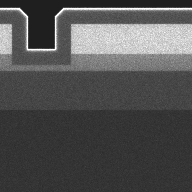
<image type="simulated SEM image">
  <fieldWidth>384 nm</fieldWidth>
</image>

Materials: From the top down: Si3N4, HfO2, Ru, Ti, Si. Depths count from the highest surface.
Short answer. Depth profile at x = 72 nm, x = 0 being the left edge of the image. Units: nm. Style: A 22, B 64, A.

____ empty 82, Si3N4 32, Ru 12, Ti 78, Si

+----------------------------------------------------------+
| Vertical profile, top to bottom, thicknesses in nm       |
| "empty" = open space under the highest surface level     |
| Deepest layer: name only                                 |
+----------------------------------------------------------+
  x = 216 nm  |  Si3N4 32, HfO2 60, Ru 34, Ti 78, Si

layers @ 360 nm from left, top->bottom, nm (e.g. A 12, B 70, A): Si3N4 32, HfO2 60, Ru 34, Ti 78, Si